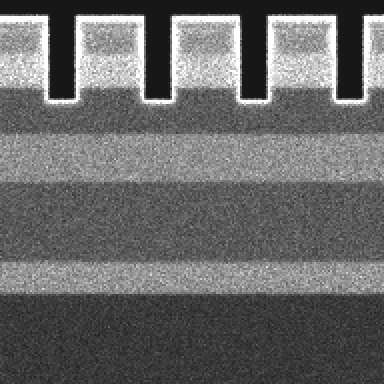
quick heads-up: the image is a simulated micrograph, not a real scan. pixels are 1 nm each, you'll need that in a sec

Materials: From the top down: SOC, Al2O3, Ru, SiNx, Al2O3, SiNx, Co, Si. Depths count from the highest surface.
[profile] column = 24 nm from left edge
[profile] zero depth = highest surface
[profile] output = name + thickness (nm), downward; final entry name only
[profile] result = SOC 12, Al2O3 26, Ru 34, SiNx 46, Al2O3 48, SiNx 80, Co 32, Si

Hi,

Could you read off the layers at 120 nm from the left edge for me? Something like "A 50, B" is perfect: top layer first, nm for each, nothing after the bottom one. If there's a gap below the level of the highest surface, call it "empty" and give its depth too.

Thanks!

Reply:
SOC 12, Al2O3 26, Ru 34, SiNx 46, Al2O3 48, SiNx 80, Co 32, Si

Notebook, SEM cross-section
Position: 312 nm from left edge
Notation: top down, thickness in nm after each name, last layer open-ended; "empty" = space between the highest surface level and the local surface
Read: SOC 12, Al2O3 26, Ru 34, SiNx 46, Al2O3 48, SiNx 80, Co 32, Si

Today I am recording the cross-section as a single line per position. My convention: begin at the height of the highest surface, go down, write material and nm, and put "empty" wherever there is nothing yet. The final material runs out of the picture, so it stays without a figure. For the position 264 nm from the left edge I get empty 84, SiNx 34, Al2O3 48, SiNx 80, Co 32, Si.